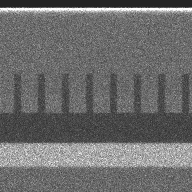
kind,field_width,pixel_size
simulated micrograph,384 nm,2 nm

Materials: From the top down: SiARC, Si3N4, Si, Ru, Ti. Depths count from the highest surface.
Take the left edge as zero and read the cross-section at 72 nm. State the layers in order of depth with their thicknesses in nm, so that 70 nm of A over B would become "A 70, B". SiARC 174, Si3N4 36, Si 60, Ru 48, Ti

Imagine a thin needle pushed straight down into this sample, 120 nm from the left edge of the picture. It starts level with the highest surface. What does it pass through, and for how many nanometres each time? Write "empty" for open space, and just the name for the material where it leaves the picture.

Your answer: SiARC 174, Si3N4 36, Si 60, Ru 48, Ti